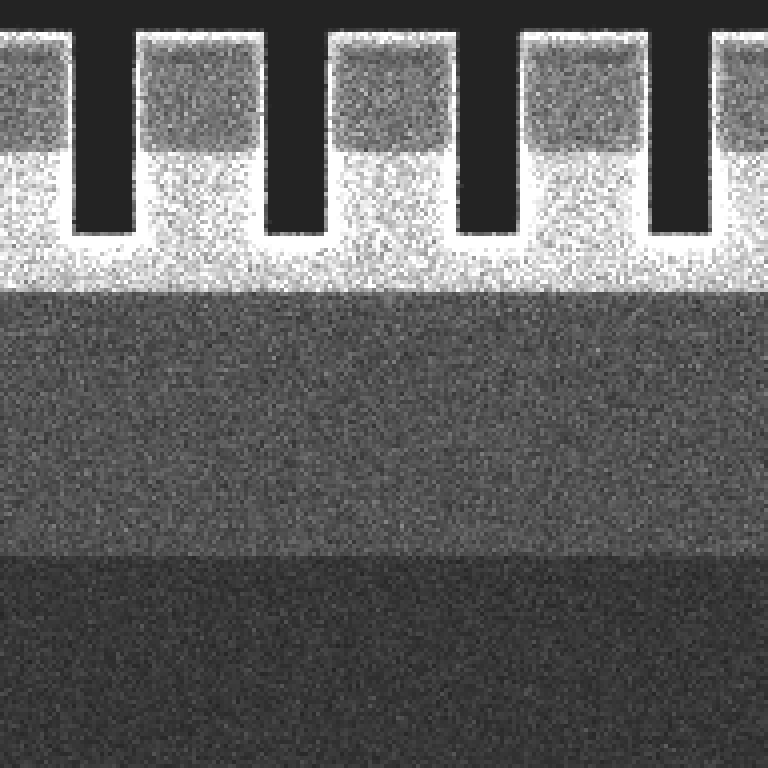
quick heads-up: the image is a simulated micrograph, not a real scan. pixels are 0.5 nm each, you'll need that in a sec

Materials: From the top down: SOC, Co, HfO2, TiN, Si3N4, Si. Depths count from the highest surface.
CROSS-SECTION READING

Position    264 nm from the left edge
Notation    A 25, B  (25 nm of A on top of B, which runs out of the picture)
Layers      SOC 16, Co 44, HfO2 70, TiN 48, Si3N4 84, Si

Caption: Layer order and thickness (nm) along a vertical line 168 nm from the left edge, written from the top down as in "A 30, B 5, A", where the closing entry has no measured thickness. SOC 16, Co 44, HfO2 70, TiN 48, Si3N4 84, Si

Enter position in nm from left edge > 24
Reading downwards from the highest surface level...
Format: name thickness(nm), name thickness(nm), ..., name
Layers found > SOC 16, Co 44, HfO2 70, TiN 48, Si3N4 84, Si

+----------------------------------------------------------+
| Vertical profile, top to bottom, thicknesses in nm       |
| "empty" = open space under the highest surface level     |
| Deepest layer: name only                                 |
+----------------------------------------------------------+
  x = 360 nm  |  SOC 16, Co 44, HfO2 70, TiN 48, Si3N4 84, Si